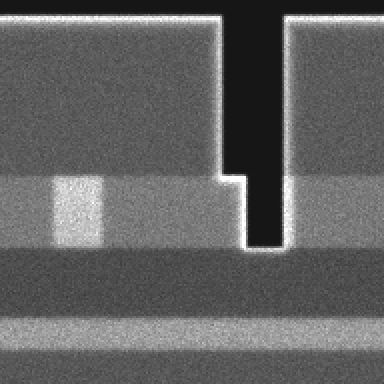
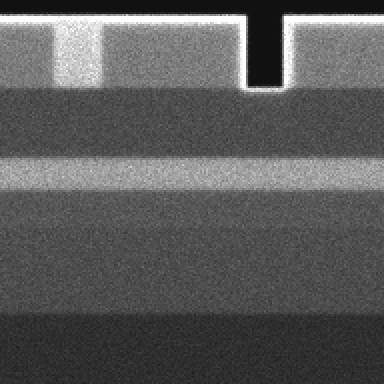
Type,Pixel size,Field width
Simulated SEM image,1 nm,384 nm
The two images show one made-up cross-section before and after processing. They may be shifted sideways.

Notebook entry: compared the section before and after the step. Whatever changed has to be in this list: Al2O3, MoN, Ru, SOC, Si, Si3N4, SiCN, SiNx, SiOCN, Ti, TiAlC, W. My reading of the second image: SOC removed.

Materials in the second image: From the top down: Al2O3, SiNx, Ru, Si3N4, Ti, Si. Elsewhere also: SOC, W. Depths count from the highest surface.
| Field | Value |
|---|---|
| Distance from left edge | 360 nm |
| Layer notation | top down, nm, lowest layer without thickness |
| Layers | Al2O3 72, SiNx 70, Ru 32, Si3N4 38, Ti 86, Si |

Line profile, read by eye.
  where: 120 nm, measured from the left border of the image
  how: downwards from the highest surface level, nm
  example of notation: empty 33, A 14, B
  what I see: Al2O3 72, SiNx 70, Ru 32, Si3N4 38, Ti 86, Si